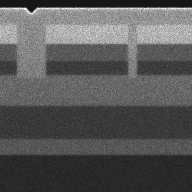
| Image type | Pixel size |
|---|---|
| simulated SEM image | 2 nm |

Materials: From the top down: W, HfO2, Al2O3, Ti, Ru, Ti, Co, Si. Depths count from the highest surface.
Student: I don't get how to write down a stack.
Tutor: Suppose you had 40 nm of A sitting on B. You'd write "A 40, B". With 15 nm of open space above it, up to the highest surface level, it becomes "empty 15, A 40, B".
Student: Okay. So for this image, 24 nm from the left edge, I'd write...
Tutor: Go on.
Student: W 34, HfO2 38, Al2O3 34, Ti 28, Ru 62, Ti 66, Co 32, Si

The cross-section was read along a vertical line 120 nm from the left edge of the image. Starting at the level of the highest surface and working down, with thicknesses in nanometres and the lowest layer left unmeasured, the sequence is W 34, HfO2 38, Al2O3 34, Ti 28, Ru 62, Ti 66, Co 32, Si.